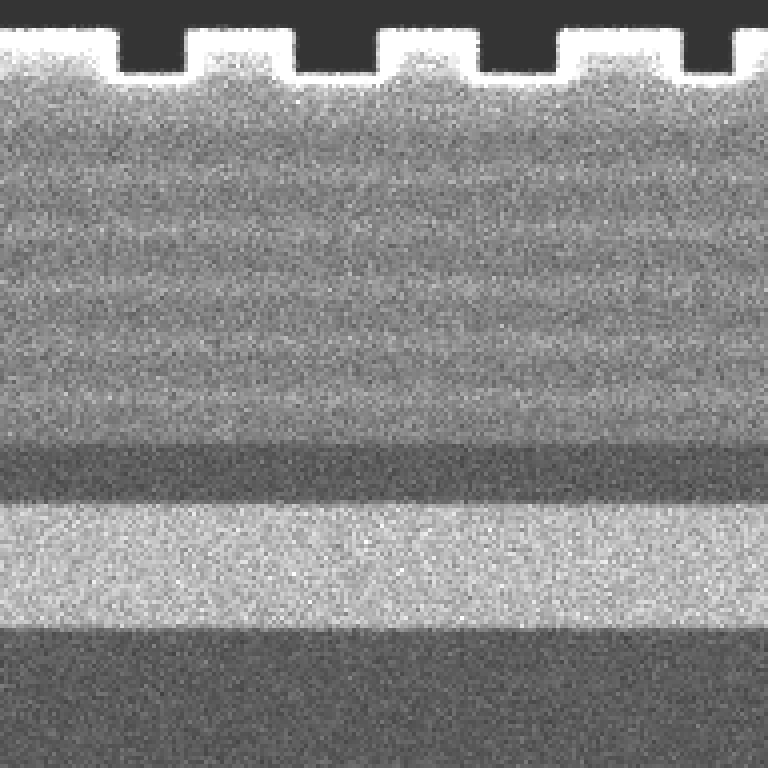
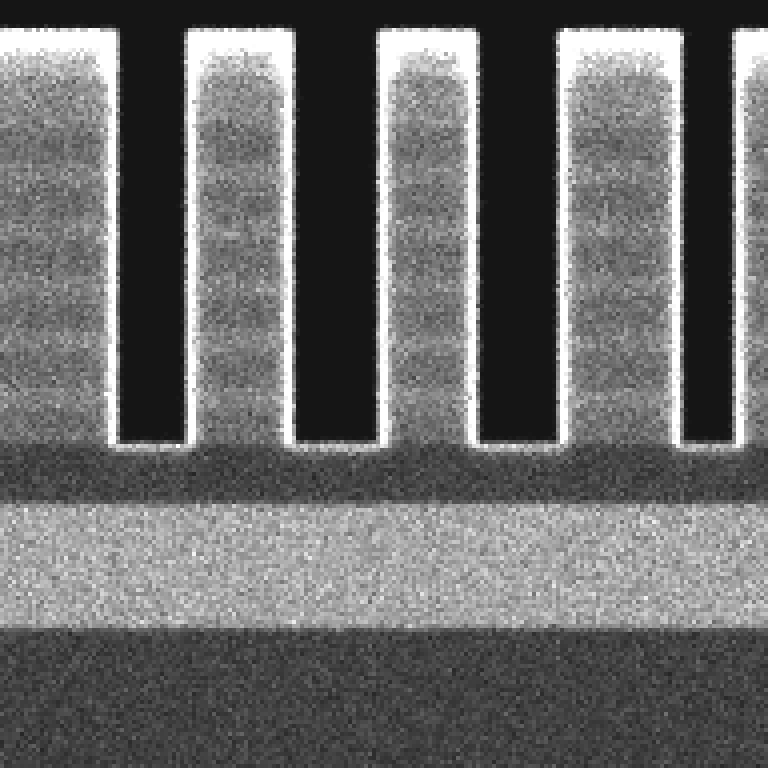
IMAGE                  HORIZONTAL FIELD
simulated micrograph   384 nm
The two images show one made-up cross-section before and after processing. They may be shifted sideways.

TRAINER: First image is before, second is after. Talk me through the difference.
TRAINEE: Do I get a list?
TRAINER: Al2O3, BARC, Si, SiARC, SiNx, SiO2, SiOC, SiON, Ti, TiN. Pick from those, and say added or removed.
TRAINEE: removed: SiNx and TiN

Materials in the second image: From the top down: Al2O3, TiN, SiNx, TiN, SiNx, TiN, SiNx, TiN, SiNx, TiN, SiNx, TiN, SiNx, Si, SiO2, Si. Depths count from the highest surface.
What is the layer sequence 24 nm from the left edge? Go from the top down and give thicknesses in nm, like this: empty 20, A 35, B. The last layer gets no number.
Al2O3 22, TiN 26, SiNx 18, TiN 10, SiNx 18, TiN 10, SiNx 18, TiN 10, SiNx 18, TiN 10, SiNx 18, TiN 10, SiNx 18, Si 30, SiO2 62, Si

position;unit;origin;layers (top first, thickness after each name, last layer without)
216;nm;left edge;Al2O3 22, TiN 26, SiNx 18, TiN 10, SiNx 18, TiN 10, SiNx 18, TiN 10, SiNx 18, TiN 10, SiNx 18, TiN 10, SiNx 18, Si 30, SiO2 62, Si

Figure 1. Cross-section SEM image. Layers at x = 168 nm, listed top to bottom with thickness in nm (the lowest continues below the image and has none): empty 206, Si 30, SiO2 62, Si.